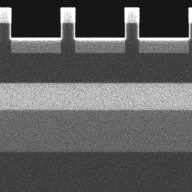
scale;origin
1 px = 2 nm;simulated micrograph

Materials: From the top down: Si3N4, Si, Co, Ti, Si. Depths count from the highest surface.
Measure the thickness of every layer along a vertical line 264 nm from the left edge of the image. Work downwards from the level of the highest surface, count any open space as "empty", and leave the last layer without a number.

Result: Co 30, Si 120, Co 54, Ti 84, Si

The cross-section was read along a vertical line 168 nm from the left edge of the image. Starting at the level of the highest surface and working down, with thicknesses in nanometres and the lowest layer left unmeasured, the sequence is empty 60, Si3N4 30, Si 60, Co 54, Ti 84, Si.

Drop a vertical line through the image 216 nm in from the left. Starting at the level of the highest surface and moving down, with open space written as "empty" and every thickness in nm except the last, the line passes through empty 60, Si3N4 30, Si 60, Co 54, Ti 84, Si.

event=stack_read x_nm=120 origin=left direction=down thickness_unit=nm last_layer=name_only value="empty 60, Si3N4 30, Si 60, Co 54, Ti 84, Si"